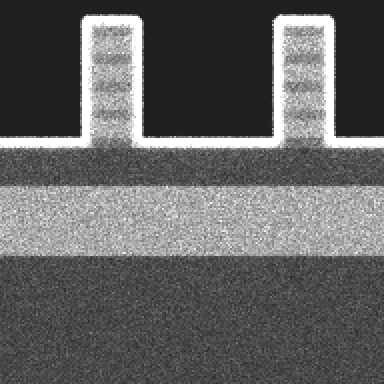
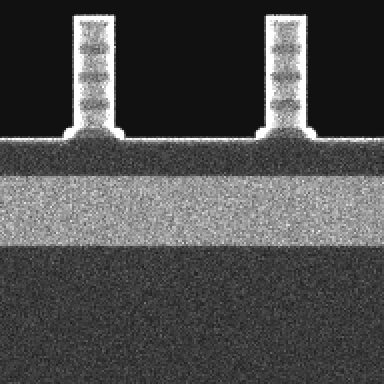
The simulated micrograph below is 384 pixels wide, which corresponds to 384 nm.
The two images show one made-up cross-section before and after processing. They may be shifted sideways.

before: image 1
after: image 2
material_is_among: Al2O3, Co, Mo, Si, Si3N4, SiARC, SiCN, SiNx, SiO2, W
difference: Al2O3, removed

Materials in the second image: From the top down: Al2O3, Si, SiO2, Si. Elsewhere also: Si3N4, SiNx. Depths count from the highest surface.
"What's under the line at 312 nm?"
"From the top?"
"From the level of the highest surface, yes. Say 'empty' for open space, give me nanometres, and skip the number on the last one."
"empty 114, Al2O3 8, Si 38, SiO2 70, Si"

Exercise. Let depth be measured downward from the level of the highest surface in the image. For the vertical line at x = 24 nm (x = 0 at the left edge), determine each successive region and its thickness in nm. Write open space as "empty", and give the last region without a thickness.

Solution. empty 122, Si 38, SiO2 70, Si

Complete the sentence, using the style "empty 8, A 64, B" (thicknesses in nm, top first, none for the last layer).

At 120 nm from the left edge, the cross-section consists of empty 114, Al2O3 8, Si 38, SiO2 70, Si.